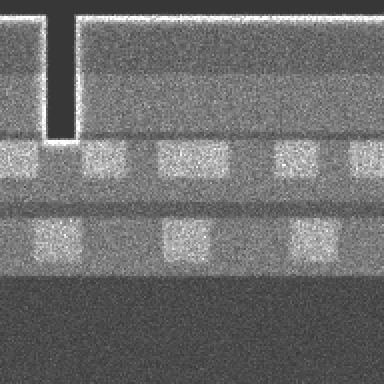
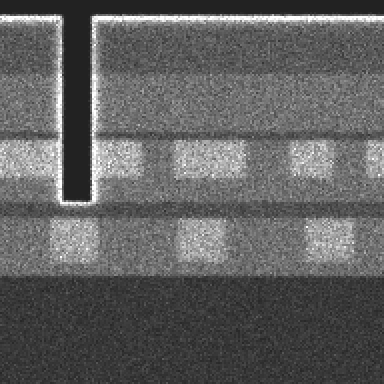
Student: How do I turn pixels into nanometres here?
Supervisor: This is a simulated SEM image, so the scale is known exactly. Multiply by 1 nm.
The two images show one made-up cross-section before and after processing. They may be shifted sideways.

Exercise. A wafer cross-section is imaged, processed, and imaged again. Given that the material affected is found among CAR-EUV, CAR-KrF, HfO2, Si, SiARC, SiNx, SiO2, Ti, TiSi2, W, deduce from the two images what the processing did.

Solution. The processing removed SiO2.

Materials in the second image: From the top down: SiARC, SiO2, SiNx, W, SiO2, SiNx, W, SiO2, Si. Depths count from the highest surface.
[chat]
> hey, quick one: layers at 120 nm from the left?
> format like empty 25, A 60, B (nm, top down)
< SiARC 58, SiO2 58, SiNx 8, W 38, SiO2 24, SiNx 16, SiO2 58, Si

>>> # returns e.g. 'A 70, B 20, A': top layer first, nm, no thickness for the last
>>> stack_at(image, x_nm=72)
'empty 186, SiNx 16, W 44, SiO2 14, Si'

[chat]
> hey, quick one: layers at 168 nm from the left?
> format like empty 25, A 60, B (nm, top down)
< SiARC 58, SiO2 58, SiNx 8, SiO2 62, SiNx 16, SiO2 58, Si